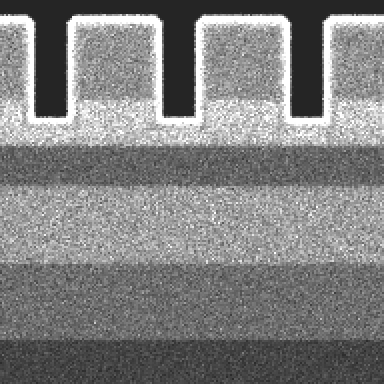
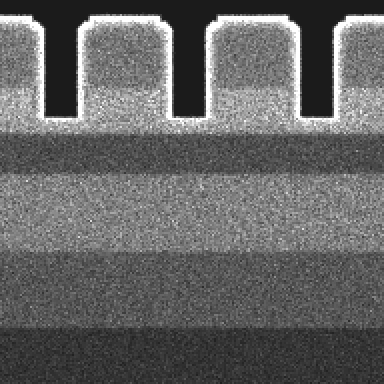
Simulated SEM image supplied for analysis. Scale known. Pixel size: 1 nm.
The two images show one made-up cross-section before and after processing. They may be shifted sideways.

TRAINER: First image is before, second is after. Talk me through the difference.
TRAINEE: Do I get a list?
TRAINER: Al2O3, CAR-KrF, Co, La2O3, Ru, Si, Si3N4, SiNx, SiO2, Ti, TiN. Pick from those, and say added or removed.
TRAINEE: removed: Al2O3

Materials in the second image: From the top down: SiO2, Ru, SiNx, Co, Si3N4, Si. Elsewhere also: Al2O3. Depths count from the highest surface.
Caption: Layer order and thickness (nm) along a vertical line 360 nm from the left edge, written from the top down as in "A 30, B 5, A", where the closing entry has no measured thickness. SiO2 72, Ru 46, SiNx 40, Co 78, Si3N4 76, Si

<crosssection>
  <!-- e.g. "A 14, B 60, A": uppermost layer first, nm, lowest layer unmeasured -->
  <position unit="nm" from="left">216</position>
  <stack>empty 6, Al2O3 96, Ru 16, SiNx 40, Co 78, Si3N4 76, Si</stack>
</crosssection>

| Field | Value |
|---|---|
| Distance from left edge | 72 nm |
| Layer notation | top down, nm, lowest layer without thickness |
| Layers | empty 102, Ru 16, SiNx 40, Co 78, Si3N4 76, Si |